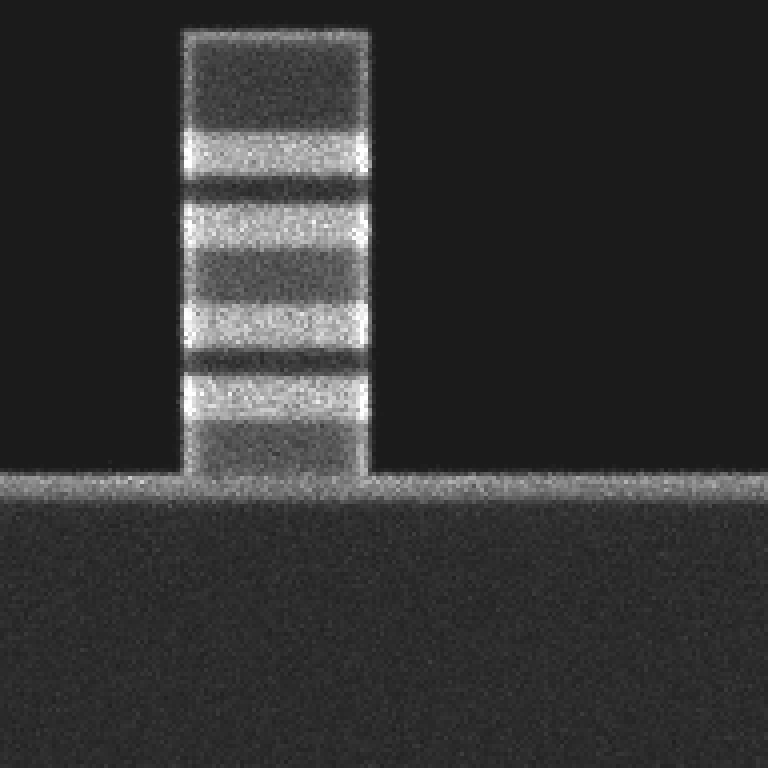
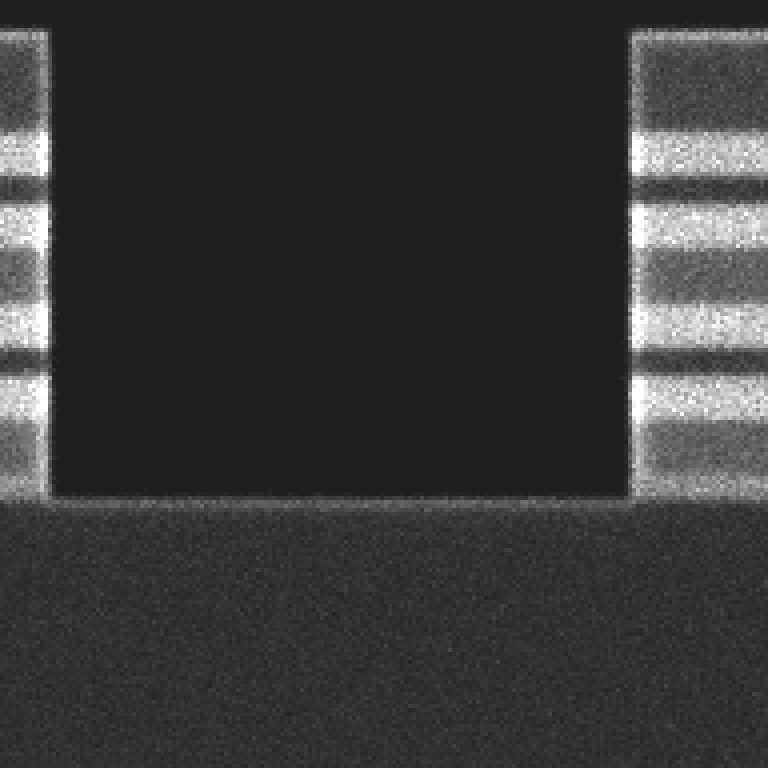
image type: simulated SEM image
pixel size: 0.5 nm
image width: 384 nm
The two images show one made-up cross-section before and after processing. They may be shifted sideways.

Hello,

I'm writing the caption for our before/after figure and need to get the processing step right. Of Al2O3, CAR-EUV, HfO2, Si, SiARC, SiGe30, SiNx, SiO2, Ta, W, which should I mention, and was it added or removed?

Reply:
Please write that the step removed W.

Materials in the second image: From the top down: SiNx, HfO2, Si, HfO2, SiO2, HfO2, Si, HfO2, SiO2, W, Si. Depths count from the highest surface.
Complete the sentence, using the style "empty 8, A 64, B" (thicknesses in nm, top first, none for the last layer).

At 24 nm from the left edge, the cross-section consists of empty 234, Si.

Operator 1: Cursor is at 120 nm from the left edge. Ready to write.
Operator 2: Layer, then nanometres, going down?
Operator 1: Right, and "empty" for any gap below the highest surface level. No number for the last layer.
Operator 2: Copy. empty 234, Si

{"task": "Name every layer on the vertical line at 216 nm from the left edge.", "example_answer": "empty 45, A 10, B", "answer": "empty 234, Si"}